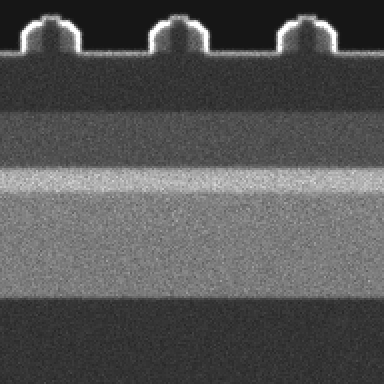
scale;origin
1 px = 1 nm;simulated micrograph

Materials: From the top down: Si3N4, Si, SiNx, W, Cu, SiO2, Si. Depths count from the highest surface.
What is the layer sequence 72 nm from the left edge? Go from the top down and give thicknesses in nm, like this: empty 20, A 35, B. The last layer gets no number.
empty 10, Si3N4 26, Si 60, SiNx 56, W 24, Cu 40, SiO2 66, Si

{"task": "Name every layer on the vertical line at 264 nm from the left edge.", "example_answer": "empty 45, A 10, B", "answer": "empty 36, Si 60, SiNx 56, W 24, Cu 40, SiO2 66, Si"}